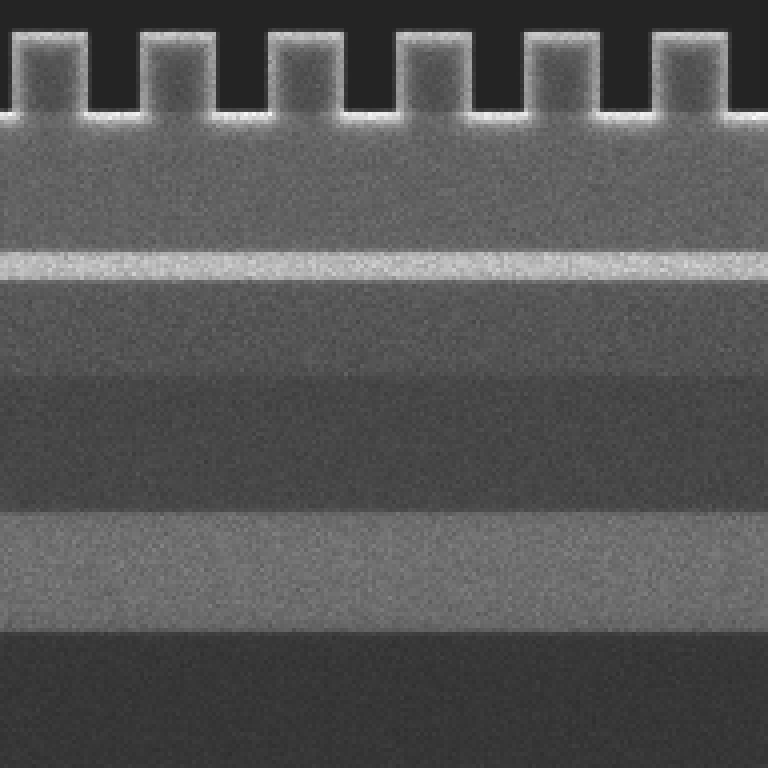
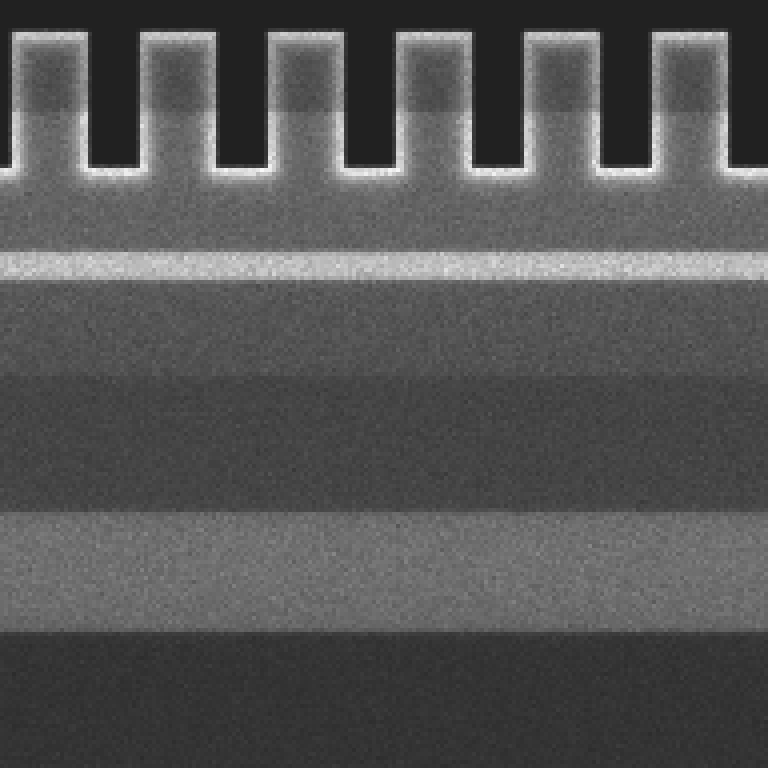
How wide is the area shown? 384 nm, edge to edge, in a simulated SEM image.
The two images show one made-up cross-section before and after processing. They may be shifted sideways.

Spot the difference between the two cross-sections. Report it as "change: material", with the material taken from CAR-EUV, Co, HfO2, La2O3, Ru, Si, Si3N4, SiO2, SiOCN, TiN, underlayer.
removed: SiO2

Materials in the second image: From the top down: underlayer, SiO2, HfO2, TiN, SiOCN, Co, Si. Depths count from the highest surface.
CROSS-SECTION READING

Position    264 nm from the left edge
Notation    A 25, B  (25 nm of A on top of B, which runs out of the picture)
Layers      underlayer 40, SiO2 70, HfO2 14, TiN 48, SiOCN 68, Co 60, Si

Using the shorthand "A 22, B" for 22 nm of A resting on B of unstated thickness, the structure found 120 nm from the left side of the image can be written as empty 68, SiO2 42, HfO2 14, TiN 48, SiOCN 68, Co 60, Si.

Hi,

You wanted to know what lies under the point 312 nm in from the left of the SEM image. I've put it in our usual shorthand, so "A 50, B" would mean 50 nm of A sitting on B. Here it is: empty 68, SiO2 42, HfO2 14, TiN 48, SiOCN 68, Co 60, Si